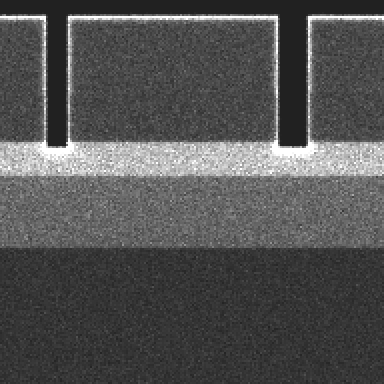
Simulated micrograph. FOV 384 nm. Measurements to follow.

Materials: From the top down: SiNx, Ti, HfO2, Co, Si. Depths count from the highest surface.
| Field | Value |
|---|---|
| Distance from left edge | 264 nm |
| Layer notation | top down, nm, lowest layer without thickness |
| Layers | SiNx 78, Ti 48, HfO2 34, Co 72, Si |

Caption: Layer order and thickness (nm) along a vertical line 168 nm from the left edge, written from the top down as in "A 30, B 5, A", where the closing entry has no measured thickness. SiNx 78, Ti 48, HfO2 34, Co 72, Si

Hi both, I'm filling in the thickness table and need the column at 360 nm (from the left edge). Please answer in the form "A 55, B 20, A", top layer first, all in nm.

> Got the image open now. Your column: SiNx 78, Ti 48, HfO2 34, Co 72, Si